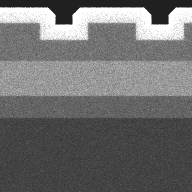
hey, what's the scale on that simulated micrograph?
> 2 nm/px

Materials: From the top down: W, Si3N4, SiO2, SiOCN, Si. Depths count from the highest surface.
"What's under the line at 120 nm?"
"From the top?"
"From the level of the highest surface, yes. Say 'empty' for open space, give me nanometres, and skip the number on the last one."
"empty 34, W 30, Si3N4 42, SiO2 70, SiOCN 44, Si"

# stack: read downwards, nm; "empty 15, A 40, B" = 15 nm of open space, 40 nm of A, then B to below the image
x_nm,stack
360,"W 64, Si3N4 42, SiO2 70, SiOCN 44, Si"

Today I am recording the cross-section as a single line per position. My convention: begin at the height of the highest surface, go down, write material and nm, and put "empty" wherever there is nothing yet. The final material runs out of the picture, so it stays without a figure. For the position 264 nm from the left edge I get W 30, Si3N4 76, SiO2 70, SiOCN 44, Si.